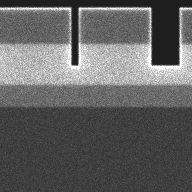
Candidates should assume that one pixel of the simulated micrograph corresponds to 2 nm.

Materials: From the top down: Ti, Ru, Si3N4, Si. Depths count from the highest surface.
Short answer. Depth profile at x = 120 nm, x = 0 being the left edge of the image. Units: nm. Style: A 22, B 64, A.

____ Ti 72, Ru 82, Si3N4 44, Si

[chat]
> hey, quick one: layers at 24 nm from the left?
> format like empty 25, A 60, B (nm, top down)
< Ti 72, Ru 82, Si3N4 44, Si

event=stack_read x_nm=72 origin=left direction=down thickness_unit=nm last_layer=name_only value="Ti 72, Ru 82, Si3N4 44, Si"